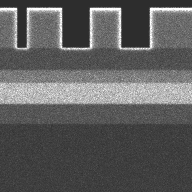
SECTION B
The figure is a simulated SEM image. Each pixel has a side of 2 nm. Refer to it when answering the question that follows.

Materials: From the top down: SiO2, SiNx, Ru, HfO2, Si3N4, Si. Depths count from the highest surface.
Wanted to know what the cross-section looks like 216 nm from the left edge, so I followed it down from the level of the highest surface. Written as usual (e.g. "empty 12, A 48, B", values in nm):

SiO2 80, SiNx 44, Ru 26, HfO2 42, Si3N4 40, Si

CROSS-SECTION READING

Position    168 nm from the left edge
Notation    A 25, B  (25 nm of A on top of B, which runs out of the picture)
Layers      empty 80, SiNx 44, Ru 26, HfO2 42, Si3N4 40, Si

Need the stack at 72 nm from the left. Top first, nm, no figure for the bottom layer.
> SiO2 80, SiNx 44, Ru 26, HfO2 42, Si3N4 40, Si